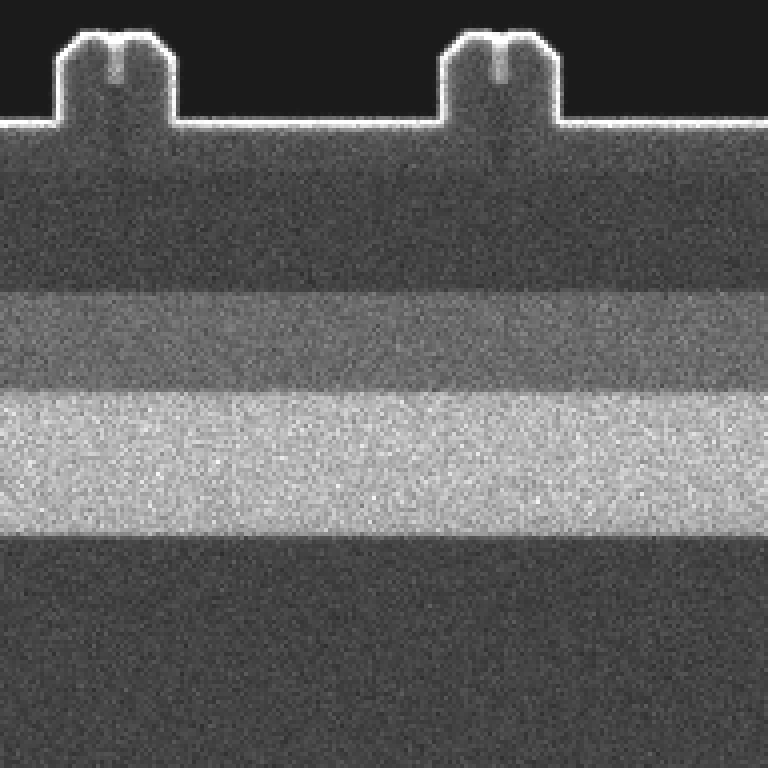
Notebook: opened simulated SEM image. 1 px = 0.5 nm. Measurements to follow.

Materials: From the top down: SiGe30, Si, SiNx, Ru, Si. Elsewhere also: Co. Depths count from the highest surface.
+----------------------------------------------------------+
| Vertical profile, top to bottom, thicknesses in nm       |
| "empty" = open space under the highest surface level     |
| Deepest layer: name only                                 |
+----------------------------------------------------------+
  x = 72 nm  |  SiGe30 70, Si 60, SiNx 50, Ru 72, Si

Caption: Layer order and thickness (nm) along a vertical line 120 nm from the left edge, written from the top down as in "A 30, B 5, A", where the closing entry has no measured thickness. empty 44, SiGe30 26, Si 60, SiNx 50, Ru 72, Si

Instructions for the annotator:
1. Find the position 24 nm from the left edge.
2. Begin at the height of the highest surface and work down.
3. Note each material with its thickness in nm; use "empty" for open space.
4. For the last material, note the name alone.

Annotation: empty 44, SiGe30 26, Si 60, SiNx 50, Ru 72, Si